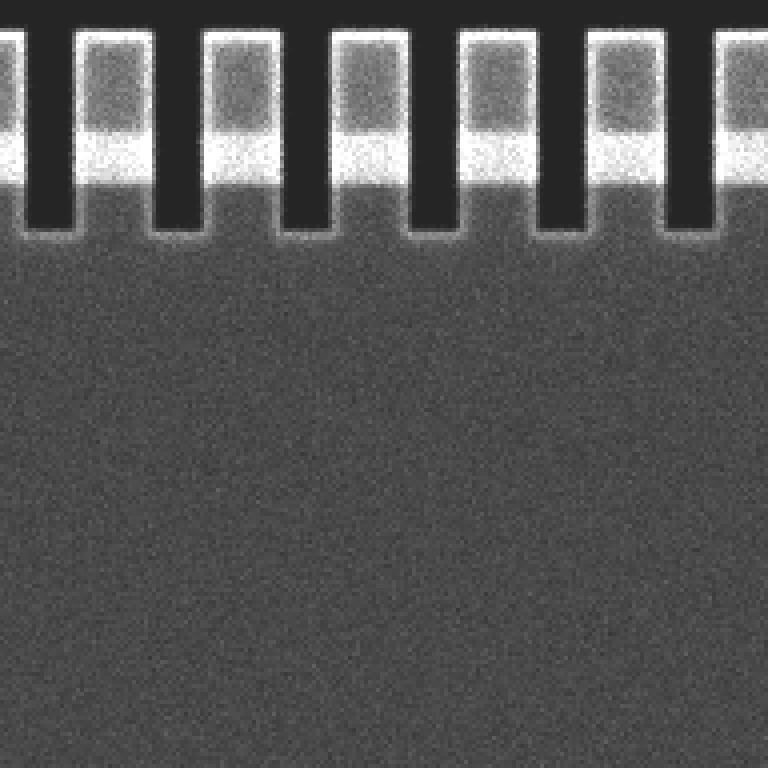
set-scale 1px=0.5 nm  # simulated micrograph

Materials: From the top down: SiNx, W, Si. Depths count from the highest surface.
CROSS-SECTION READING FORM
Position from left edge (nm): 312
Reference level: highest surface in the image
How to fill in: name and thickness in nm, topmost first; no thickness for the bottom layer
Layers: SiNx 50, W 26, Si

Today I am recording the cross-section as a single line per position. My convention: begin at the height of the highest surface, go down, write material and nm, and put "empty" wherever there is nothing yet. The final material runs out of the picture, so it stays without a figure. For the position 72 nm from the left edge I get SiNx 50, W 26, Si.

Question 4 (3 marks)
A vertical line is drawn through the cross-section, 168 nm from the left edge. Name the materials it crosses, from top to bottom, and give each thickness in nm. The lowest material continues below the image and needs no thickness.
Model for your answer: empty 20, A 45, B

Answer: SiNx 50, W 26, Si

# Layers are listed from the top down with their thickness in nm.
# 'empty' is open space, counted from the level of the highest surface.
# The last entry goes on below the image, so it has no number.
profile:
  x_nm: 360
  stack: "SiNx 50, W 26, Si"